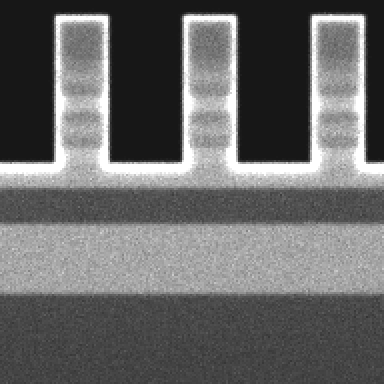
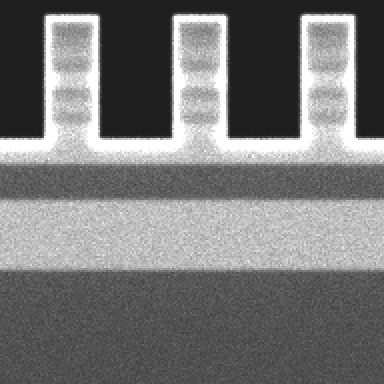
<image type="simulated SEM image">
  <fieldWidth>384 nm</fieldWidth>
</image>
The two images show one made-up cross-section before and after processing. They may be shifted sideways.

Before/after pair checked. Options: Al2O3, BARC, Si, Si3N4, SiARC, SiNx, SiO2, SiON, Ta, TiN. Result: removed SiNx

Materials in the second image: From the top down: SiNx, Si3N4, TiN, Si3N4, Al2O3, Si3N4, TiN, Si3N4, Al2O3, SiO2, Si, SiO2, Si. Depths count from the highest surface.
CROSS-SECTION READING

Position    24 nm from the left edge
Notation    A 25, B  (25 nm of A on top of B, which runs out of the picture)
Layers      empty 124, SiO2 24, Si 36, SiO2 70, Si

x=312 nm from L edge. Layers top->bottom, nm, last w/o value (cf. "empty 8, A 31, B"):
SiNx 20, Si3N4 12, TiN 12, Si3N4 12, Al2O3 16, Si3N4 12, TiN 12, Si3N4 12, Al2O3 16, SiO2 24, Si 36, SiO2 70, Si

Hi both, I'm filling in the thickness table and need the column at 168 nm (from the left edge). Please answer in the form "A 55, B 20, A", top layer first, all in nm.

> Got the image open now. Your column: empty 124, SiO2 24, Si 36, SiO2 70, Si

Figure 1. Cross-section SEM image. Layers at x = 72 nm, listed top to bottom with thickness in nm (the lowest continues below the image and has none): SiNx 20, Si3N4 12, TiN 12, Si3N4 12, Al2O3 16, Si3N4 12, TiN 12, Si3N4 12, Al2O3 16, SiO2 24, Si 36, SiO2 70, Si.